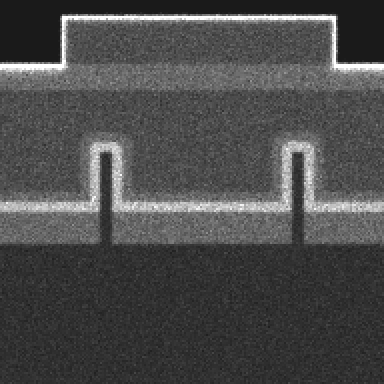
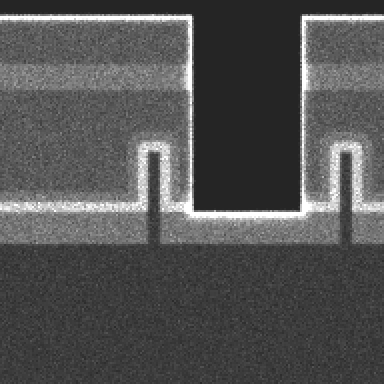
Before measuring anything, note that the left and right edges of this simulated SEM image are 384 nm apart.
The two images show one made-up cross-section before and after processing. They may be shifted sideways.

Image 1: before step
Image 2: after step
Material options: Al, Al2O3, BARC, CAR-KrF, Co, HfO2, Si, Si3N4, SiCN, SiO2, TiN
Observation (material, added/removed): Al2O3 and Co and HfO2 and TiN, removed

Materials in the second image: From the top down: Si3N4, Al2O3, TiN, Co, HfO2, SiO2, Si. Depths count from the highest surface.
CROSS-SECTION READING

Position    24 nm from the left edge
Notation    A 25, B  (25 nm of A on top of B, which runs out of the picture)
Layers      Si3N4 48, Al2O3 26, TiN 102, Co 10, HfO2 10, SiO2 32, Si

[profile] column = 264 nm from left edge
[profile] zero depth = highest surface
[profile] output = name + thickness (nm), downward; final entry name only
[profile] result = empty 196, SiO2 32, Si